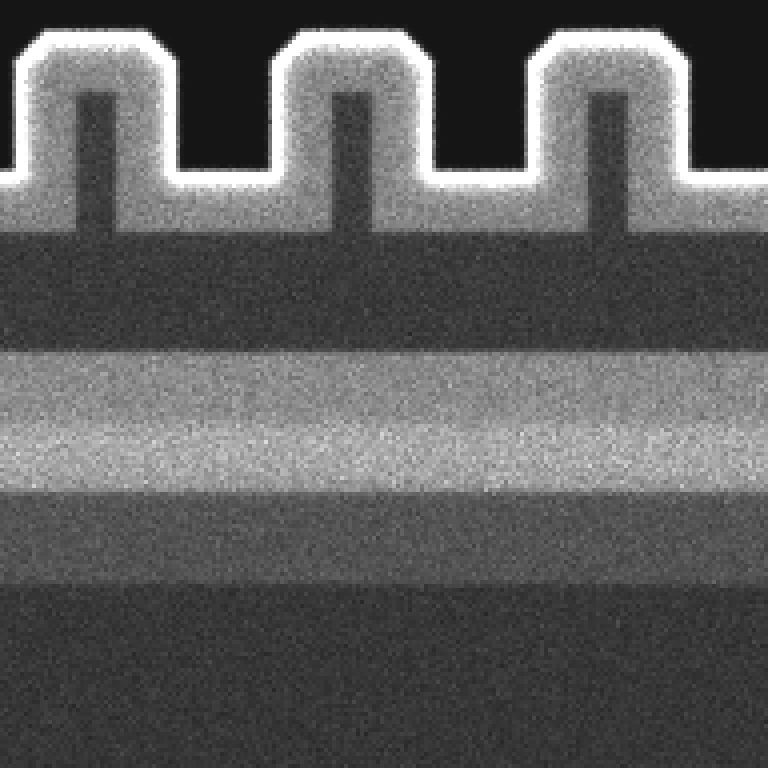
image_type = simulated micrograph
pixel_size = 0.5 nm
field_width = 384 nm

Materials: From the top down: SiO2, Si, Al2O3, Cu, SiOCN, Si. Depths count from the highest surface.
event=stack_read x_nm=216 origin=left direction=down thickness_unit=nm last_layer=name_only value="empty 70, SiO2 30, Si 60, Al2O3 36, Cu 34, SiOCN 46, Si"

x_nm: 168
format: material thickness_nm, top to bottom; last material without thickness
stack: SiO2 30, Si 130, Al2O3 36, Cu 34, SiOCN 46, Si